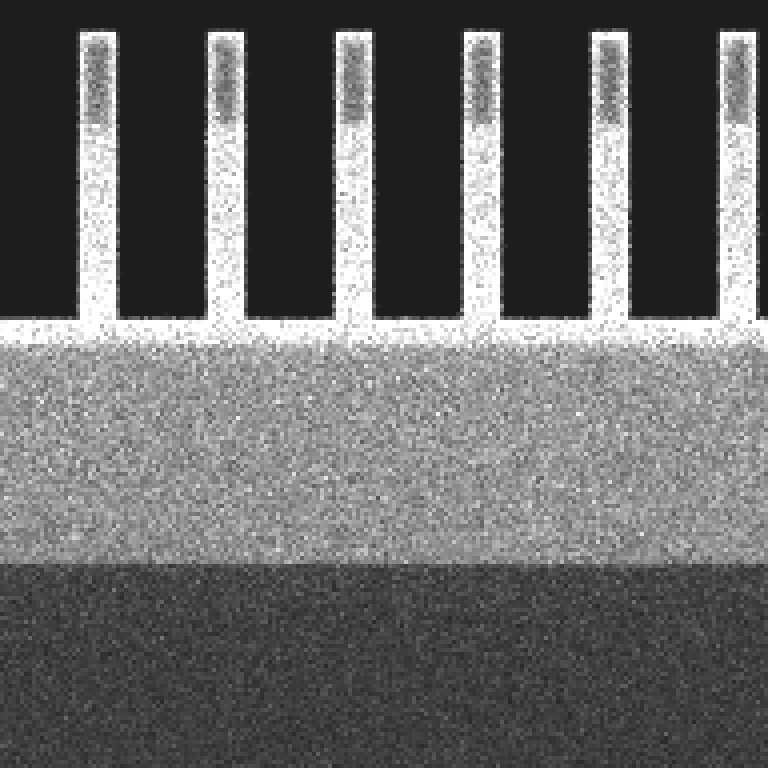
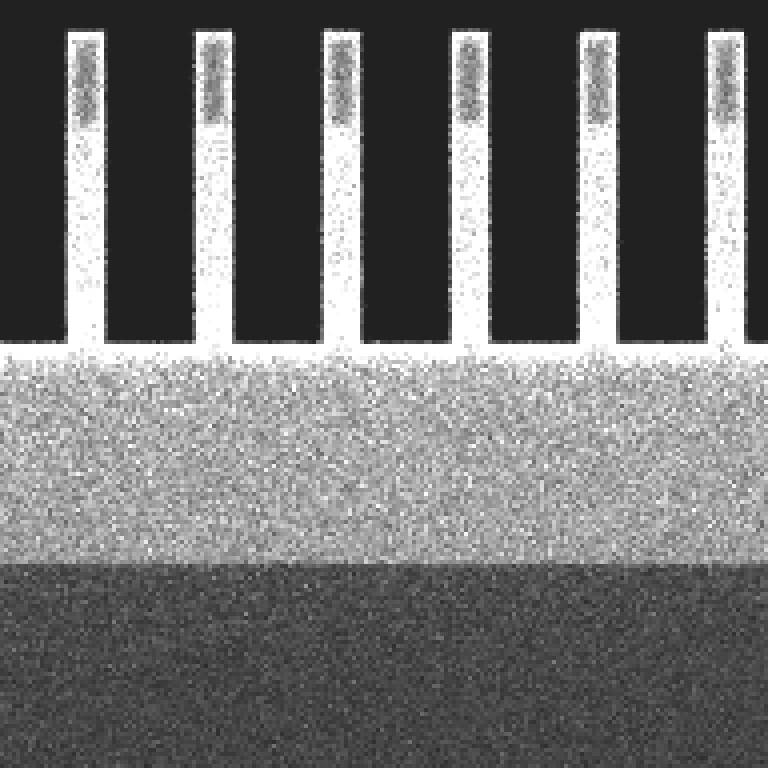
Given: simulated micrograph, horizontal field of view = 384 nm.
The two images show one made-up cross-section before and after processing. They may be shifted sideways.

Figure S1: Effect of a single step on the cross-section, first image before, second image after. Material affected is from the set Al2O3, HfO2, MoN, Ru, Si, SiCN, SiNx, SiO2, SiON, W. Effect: removed Ru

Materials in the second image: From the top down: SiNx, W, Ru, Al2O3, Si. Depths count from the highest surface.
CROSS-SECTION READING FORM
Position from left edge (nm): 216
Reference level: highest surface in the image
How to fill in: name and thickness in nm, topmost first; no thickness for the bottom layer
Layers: empty 156, Al2O3 110, Si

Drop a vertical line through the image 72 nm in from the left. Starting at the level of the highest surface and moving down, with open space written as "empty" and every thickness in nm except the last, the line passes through empty 156, Al2O3 110, Si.